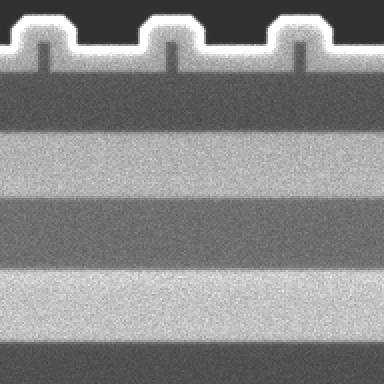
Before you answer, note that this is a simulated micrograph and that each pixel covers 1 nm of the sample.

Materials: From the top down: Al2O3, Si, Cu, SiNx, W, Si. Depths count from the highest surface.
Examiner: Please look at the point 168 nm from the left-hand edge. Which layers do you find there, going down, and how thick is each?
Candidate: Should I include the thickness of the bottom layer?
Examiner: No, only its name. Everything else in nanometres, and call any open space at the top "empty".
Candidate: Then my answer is Al2O3 26, Si 90, Cu 66, SiNx 72, W 72, Si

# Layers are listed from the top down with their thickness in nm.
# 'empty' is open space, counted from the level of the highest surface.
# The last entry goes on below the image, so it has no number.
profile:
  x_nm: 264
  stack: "empty 30, Al2O3 26, Si 60, Cu 66, SiNx 72, W 72, Si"